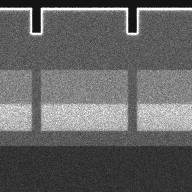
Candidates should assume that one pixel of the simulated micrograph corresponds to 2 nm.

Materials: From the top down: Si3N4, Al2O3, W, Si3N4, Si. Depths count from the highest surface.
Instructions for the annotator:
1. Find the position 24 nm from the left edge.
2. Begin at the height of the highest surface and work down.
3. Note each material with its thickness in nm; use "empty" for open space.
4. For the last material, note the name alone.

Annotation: Si3N4 124, Al2O3 68, W 54, Si3N4 30, Si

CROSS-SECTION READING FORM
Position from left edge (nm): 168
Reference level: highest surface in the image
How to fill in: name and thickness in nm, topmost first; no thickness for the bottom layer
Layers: Si3N4 124, Al2O3 68, W 54, Si3N4 30, Si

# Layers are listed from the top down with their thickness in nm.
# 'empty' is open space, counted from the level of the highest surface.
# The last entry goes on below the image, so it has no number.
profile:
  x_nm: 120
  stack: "Si3N4 124, Al2O3 68, W 54, Si3N4 30, Si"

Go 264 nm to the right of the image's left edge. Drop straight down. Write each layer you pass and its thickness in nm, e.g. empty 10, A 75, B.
empty 50, Si3N4 226, Si